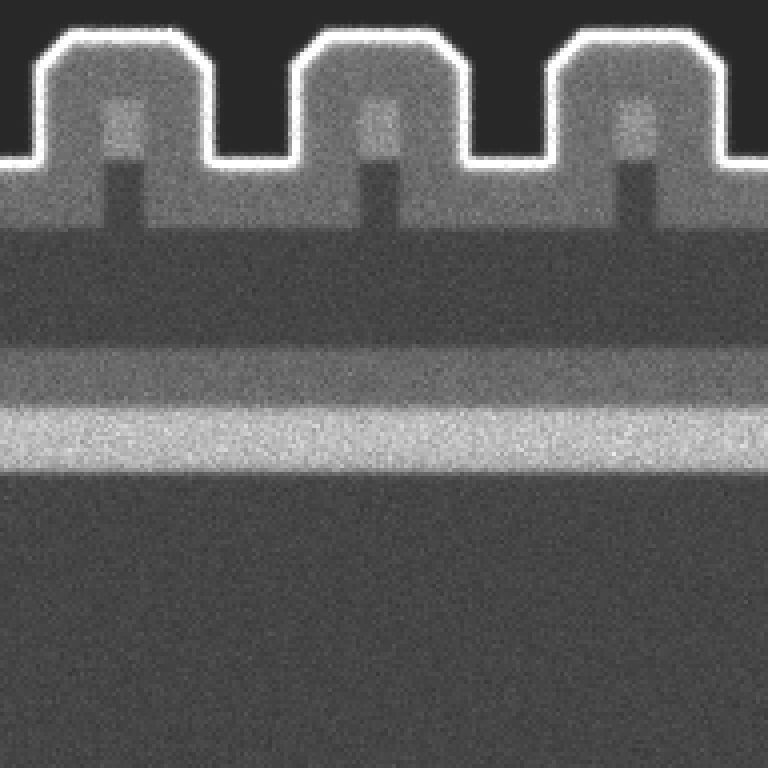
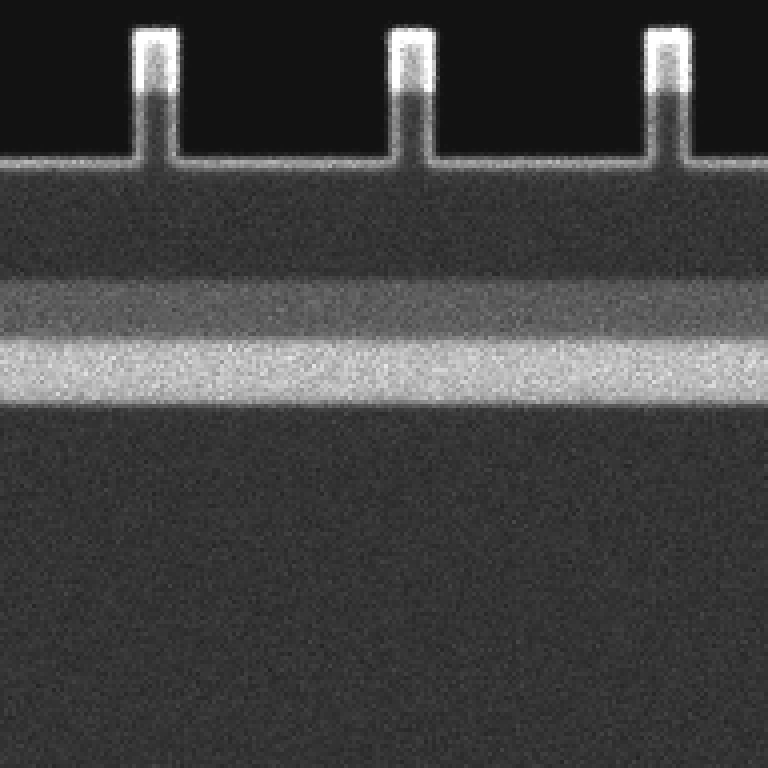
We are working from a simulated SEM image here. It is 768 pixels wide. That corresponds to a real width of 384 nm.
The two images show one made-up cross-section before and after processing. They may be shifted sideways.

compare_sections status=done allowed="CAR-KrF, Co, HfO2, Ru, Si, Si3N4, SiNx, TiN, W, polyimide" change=removed material="Si3N4"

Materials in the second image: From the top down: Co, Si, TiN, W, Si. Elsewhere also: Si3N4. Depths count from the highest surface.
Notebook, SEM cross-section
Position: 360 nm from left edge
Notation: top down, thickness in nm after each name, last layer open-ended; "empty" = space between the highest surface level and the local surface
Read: empty 64, Si 60, TiN 30, W 32, Si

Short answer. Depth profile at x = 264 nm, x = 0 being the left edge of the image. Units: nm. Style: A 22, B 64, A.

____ empty 64, Si 60, TiN 30, W 32, Si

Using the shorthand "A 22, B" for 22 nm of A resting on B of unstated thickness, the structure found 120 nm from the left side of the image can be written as empty 64, Si 60, TiN 30, W 32, Si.